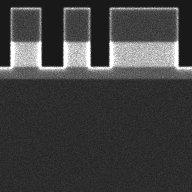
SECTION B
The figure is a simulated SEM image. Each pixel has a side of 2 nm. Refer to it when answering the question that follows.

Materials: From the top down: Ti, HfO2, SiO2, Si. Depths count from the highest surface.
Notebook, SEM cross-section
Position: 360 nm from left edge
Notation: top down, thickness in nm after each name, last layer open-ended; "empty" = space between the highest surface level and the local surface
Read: empty 118, SiO2 24, Si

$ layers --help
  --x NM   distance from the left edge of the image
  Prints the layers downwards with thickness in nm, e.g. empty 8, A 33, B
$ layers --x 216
empty 118, SiO2 24, Si